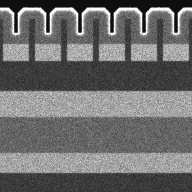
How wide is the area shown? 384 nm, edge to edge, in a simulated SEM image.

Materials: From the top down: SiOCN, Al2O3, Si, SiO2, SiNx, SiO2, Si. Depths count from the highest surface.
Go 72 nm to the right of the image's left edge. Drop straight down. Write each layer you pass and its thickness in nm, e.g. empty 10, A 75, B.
SiOCN 72, Al2O3 34, Si 60, SiO2 52, SiNx 72, SiO2 40, Si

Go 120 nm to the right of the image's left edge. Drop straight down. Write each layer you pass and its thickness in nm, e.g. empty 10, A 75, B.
SiOCN 72, Al2O3 34, Si 60, SiO2 52, SiNx 72, SiO2 40, Si